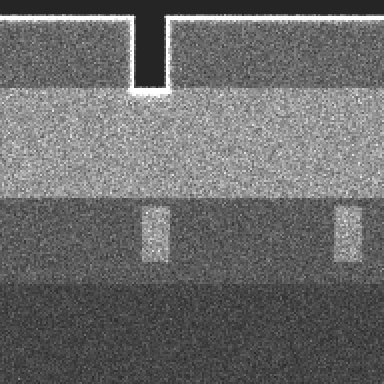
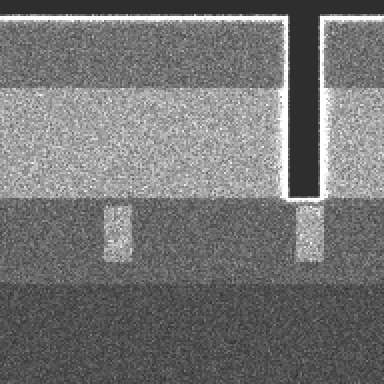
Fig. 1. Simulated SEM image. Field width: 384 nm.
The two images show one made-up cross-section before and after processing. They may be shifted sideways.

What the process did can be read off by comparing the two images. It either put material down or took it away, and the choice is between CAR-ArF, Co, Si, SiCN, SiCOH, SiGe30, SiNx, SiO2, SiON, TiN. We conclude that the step removed SiO2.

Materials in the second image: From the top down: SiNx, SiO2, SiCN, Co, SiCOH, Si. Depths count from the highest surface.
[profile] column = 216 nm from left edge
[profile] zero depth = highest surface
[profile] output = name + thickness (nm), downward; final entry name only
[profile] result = SiNx 72, SiO2 110, SiCN 8, SiCOH 78, Si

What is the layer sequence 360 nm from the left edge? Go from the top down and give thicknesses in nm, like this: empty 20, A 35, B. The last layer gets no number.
SiNx 72, SiO2 110, SiCN 8, SiCOH 78, Si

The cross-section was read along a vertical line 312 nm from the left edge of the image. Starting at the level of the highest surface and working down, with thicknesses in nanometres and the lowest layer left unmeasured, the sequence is empty 182, SiCN 8, Co 56, SiCOH 22, Si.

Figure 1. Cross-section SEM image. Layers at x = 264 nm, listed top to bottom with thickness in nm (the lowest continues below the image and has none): SiNx 72, SiO2 110, SiCN 8, SiCOH 78, Si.